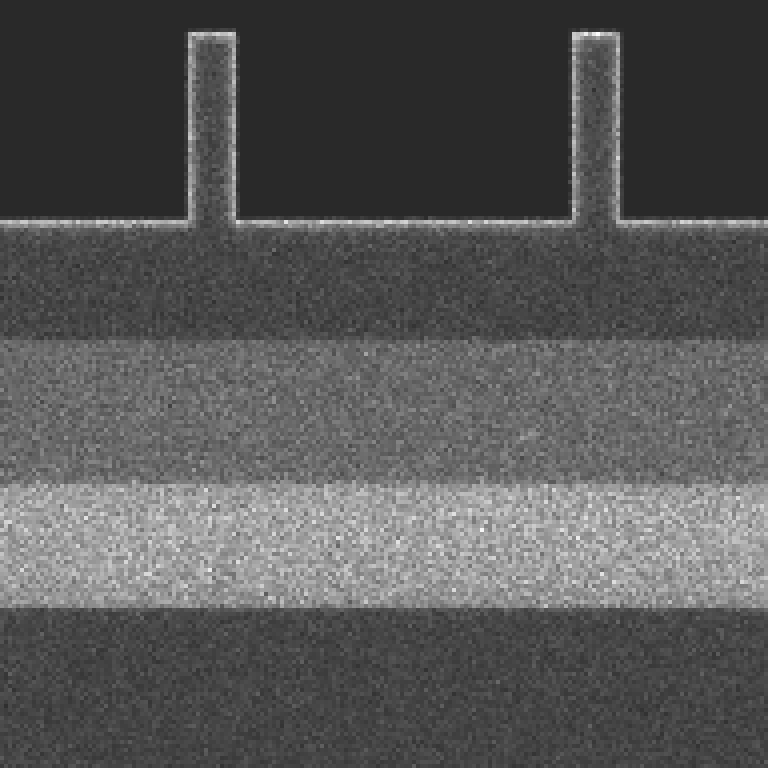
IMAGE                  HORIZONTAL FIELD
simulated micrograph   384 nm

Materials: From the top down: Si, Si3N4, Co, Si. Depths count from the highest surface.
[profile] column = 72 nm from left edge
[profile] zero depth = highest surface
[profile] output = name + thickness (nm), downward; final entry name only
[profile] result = empty 94, Si 60, Si3N4 72, Co 62, Si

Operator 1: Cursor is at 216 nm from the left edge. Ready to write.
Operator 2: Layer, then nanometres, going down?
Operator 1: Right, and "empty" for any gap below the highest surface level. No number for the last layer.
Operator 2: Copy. empty 94, Si 60, Si3N4 72, Co 62, Si